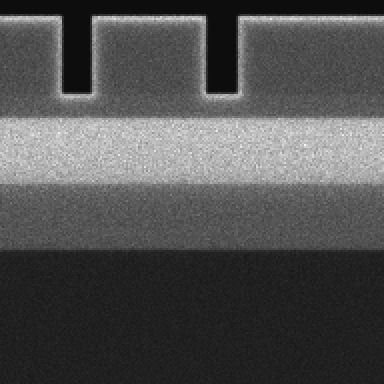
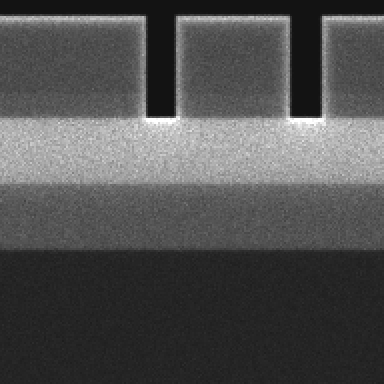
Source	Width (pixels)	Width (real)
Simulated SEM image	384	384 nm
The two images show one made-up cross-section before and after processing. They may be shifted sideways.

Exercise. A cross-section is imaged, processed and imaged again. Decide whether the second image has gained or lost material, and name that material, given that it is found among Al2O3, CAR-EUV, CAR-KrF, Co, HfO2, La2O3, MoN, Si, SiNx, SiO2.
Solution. removed: Al2O3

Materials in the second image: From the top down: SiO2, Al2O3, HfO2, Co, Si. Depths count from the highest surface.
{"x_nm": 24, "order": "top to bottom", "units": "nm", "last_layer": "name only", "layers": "SiO2 78, Al2O3 24, HfO2 66, Co 66, Si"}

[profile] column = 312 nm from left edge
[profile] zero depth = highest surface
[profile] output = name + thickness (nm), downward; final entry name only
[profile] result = empty 102, HfO2 66, Co 66, Si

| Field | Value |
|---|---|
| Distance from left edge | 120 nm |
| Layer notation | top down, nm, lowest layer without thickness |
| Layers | SiO2 78, Al2O3 24, HfO2 66, Co 66, Si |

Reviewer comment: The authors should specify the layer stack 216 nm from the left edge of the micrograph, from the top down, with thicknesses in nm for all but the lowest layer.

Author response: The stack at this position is SiO2 78, Al2O3 24, HfO2 66, Co 66, Si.